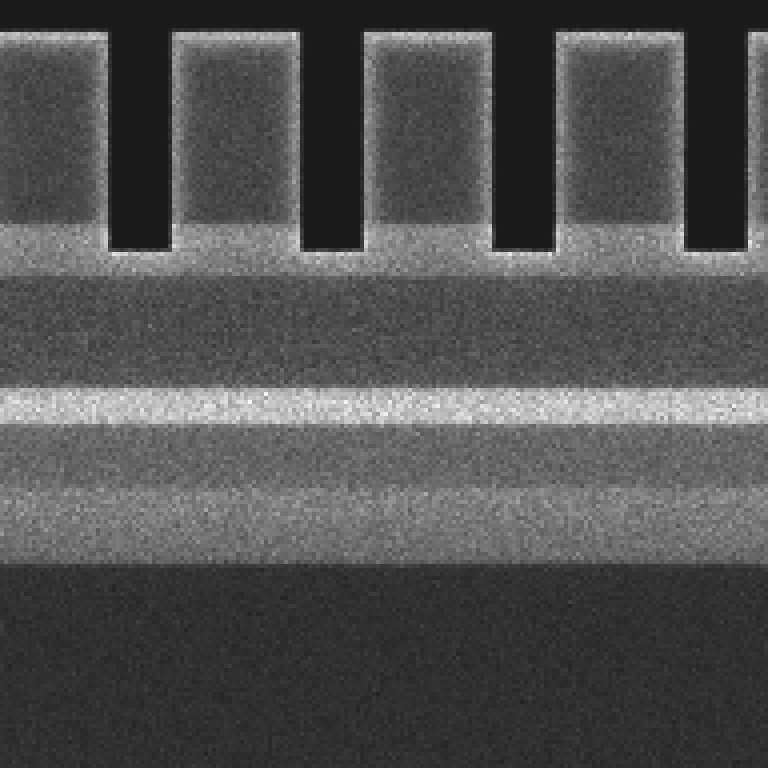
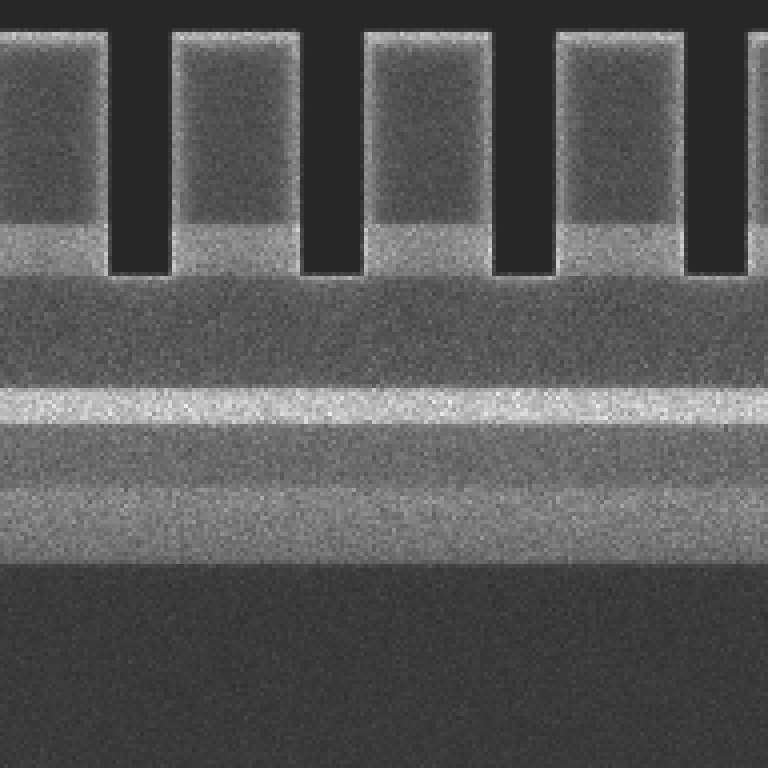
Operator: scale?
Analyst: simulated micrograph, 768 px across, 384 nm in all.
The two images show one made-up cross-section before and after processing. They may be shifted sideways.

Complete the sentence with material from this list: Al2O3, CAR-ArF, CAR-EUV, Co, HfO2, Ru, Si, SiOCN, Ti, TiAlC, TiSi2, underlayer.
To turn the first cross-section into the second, Ru must be removed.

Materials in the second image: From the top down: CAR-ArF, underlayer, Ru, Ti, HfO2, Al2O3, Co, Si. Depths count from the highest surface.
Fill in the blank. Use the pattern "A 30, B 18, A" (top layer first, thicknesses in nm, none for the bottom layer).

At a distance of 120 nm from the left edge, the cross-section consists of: CAR-ArF 60, underlayer 36, Ru 26, Ti 56, HfO2 18, Al2O3 32, Co 38, Si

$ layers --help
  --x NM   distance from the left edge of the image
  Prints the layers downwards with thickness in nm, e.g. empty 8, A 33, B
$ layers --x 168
empty 122, Ti 56, HfO2 18, Al2O3 32, Co 38, Si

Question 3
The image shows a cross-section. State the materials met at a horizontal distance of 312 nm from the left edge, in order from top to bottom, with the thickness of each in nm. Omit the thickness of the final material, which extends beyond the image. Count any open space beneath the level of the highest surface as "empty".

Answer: CAR-ArF 60, underlayer 36, Ru 26, Ti 56, HfO2 18, Al2O3 32, Co 38, Si